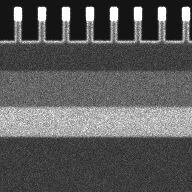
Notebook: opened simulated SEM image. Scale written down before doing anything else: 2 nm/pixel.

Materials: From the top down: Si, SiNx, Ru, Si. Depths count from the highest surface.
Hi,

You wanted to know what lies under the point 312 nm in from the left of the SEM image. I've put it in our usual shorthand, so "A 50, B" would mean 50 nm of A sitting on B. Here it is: empty 66, Si 60, SiNx 72, Ru 60, Si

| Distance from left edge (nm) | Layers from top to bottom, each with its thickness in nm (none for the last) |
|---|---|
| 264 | empty 66, Si 60, SiNx 72, Ru 60, Si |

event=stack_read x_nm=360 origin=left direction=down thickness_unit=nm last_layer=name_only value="empty 66, Si 60, SiNx 72, Ru 60, Si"